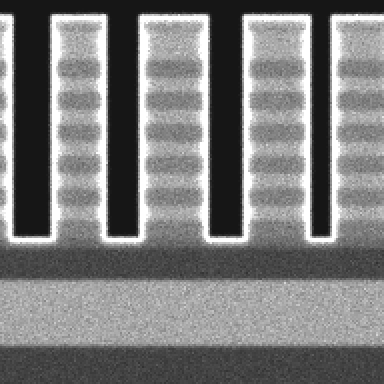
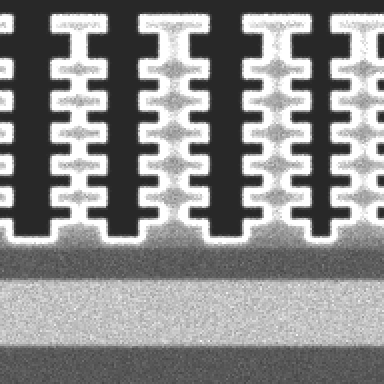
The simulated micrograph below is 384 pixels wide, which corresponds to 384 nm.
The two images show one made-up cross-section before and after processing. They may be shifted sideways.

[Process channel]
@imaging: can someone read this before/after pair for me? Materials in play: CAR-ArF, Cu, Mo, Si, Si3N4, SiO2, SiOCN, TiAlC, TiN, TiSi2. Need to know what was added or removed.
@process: SiO2 removed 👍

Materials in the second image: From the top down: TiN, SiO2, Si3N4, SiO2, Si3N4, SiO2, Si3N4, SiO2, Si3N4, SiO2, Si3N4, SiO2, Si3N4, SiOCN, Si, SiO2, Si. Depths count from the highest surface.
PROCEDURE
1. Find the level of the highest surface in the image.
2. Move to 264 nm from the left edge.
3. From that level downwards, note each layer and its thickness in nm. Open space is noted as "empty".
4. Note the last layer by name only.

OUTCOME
TiN 16, SiO2 28, Si3N4 18, SiO2 14, Si3N4 18, SiO2 14, Si3N4 18, SiO2 14, Si3N4 18, SiO2 14, Si3N4 18, SiO2 14, Si3N4 18, SiOCN 10, Si 32, SiO2 66, Si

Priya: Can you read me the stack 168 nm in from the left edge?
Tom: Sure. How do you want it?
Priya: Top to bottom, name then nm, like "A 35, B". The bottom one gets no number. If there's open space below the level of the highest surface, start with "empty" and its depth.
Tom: TiN 16, SiO2 28, Si3N4 18, SiO2 14, Si3N4 18, SiO2 14, Si3N4 18, SiO2 14, Si3N4 18, SiO2 14, Si3N4 18, SiO2 14, Si3N4 18, SiOCN 10, Si 32, SiO2 66, Si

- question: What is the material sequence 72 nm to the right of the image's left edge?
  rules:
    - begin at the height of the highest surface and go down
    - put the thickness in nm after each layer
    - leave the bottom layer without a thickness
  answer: TiN 16, SiO2 28, Si3N4 18, SiO2 14, Si3N4 18, SiO2 14, Si3N4 18, SiO2 14, Si3N4 18, SiO2 14, Si3N4 18, SiO2 14, Si3N4 18, SiOCN 10, Si 32, SiO2 66, Si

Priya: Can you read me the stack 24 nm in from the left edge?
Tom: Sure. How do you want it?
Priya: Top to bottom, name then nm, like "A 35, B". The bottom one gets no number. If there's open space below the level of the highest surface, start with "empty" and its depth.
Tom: empty 222, SiOCN 10, Si 32, SiO2 66, Si